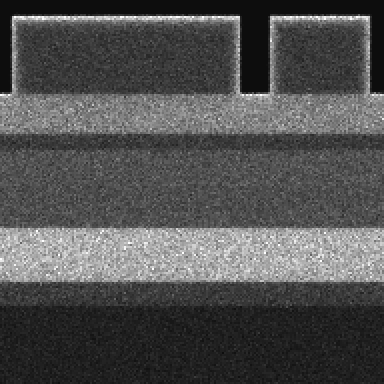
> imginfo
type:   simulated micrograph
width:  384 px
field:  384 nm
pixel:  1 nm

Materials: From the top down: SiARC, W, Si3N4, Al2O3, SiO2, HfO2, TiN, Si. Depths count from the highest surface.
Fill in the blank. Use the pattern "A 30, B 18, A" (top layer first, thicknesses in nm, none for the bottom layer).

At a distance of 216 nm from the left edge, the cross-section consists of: SiARC 78, W 40, Si3N4 16, Al2O3 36, SiO2 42, HfO2 54, TiN 24, Si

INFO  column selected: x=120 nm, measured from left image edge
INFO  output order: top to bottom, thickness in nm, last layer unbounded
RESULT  SiARC 78, W 40, Si3N4 16, Al2O3 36, SiO2 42, HfO2 54, TiN 24, Si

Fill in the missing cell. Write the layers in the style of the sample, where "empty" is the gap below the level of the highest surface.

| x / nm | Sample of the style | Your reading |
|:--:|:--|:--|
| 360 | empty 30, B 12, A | SiARC 78, W 40, Si3N4 16, Al2O3 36, SiO2 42, HfO2 54, TiN 24, Si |